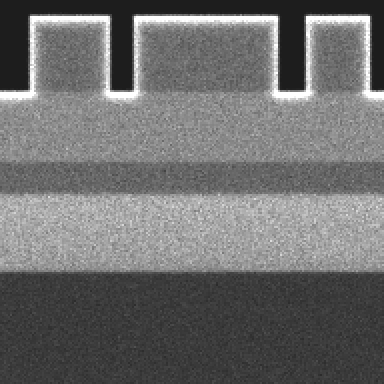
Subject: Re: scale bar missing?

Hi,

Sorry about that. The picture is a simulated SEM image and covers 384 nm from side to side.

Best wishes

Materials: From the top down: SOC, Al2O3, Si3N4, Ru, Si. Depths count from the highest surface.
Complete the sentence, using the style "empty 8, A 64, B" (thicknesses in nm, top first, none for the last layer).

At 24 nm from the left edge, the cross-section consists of empty 76, Al2O3 70, Si3N4 32, Ru 78, Si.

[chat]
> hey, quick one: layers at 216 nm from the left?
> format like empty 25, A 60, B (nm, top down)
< SOC 76, Al2O3 70, Si3N4 32, Ru 78, Si